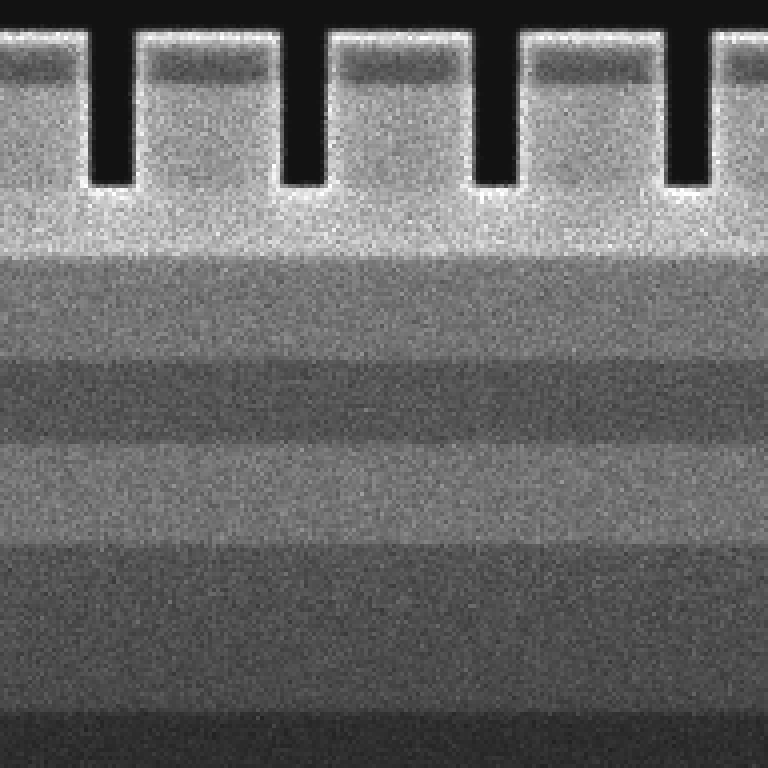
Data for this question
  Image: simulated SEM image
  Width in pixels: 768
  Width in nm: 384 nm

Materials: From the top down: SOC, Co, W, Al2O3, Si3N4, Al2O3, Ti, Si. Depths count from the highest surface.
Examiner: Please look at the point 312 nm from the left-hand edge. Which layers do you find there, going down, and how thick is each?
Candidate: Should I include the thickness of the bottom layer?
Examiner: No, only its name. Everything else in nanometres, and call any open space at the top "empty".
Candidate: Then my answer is SOC 26, Co 52, W 34, Al2O3 52, Si3N4 42, Al2O3 50, Ti 84, Si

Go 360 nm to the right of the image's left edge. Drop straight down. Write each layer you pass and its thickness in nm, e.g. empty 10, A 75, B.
SOC 26, Co 52, W 34, Al2O3 52, Si3N4 42, Al2O3 50, Ti 84, Si